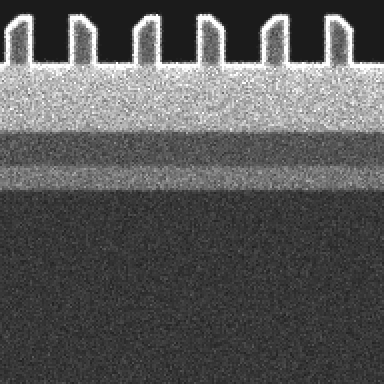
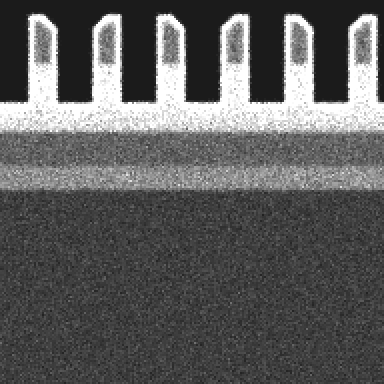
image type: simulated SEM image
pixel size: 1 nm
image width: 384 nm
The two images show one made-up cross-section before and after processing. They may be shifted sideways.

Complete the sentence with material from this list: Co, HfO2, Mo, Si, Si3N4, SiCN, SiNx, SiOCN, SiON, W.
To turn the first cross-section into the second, W must be removed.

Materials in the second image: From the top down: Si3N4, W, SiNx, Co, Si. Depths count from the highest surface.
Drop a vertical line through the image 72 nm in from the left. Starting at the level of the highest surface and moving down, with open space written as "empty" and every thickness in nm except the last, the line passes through empty 88, W 28, SiNx 34, Co 24, Si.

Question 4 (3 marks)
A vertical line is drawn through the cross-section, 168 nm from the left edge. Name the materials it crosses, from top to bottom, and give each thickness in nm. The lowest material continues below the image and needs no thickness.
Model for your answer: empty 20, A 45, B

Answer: Si3N4 48, W 68, SiNx 34, Co 24, Si